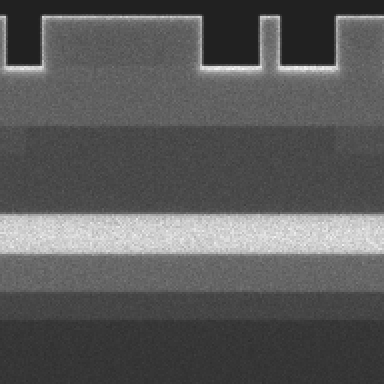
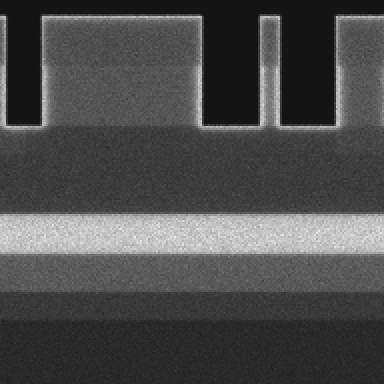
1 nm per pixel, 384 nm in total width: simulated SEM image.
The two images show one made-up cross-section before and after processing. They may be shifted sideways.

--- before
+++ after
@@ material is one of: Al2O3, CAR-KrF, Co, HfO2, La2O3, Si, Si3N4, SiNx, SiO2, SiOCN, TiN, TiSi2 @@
SiO2 removed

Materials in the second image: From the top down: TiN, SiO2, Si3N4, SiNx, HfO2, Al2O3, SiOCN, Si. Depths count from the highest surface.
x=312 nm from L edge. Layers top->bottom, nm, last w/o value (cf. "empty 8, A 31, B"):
empty 110, SiNx 88, HfO2 40, Al2O3 38, SiOCN 28, Si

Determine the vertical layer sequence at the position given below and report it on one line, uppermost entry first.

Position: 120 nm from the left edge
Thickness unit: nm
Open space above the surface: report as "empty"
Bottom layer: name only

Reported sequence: TiN 50, SiO2 60, SiNx 88, HfO2 40, Al2O3 38, SiOCN 28, Si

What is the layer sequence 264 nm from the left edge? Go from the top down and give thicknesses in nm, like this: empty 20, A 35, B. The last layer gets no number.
TiN 50, SiO2 60, SiNx 88, HfO2 40, Al2O3 38, SiOCN 28, Si